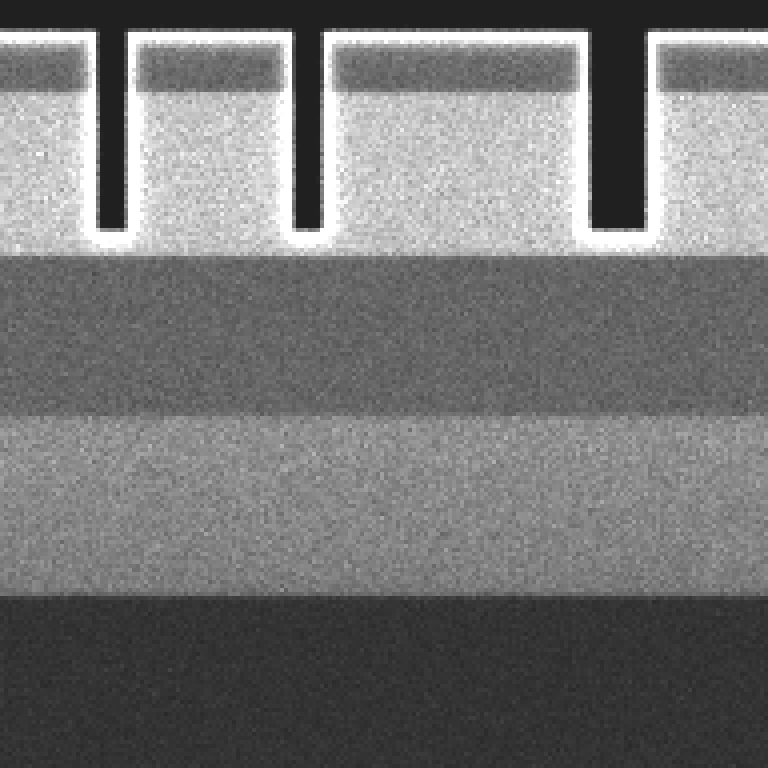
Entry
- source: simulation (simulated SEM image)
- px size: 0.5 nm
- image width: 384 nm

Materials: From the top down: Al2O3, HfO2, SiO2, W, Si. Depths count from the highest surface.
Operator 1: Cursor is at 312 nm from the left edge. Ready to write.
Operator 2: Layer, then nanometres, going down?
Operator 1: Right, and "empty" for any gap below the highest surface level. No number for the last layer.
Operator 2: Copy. empty 100, HfO2 12, SiO2 80, W 90, Si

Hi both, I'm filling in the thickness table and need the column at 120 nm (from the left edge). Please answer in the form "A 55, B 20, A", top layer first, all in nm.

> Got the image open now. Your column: Al2O3 30, HfO2 82, SiO2 80, W 90, Si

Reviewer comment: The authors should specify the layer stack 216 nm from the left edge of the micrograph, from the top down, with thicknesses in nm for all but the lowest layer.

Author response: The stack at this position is Al2O3 30, HfO2 82, SiO2 80, W 90, Si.